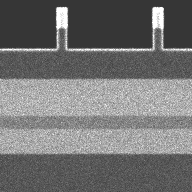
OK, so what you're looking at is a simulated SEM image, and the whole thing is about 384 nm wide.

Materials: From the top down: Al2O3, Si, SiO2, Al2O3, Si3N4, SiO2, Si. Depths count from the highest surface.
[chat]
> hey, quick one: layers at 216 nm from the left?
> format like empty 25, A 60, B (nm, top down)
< empty 82, Si 60, SiO2 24, Al2O3 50, Si3N4 26, SiO2 50, Si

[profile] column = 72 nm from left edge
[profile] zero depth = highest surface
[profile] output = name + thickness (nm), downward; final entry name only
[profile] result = empty 82, Si 60, SiO2 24, Al2O3 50, Si3N4 26, SiO2 50, Si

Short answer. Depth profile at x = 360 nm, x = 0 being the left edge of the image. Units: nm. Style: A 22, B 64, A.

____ empty 82, Si 60, SiO2 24, Al2O3 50, Si3N4 26, SiO2 50, Si